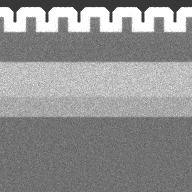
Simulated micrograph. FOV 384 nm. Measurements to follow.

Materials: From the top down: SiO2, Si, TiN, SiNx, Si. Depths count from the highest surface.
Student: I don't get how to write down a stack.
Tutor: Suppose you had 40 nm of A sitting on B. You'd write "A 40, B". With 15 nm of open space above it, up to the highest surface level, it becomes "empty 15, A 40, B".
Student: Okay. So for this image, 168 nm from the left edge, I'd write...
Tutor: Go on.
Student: empty 2, SiO2 46, Si 60, TiN 70, SiNx 40, Si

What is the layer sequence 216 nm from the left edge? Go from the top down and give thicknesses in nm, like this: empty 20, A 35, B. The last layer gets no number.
empty 8, SiO2 40, Si 60, TiN 70, SiNx 40, Si